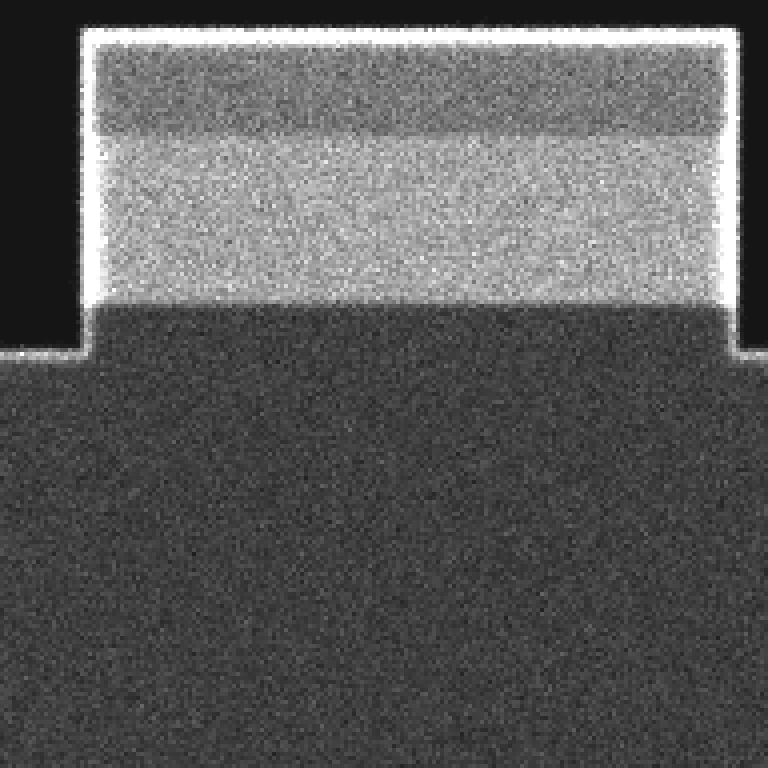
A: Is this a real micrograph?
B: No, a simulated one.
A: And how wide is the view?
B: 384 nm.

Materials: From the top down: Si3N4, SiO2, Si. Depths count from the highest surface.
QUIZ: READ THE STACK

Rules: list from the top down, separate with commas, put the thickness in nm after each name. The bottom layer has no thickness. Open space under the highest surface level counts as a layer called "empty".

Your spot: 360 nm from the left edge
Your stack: Si3N4 52, SiO2 84, Si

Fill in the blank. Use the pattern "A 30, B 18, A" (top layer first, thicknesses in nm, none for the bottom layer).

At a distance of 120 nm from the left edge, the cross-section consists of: Si3N4 52, SiO2 84, Si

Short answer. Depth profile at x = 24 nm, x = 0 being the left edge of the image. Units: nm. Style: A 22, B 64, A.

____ empty 160, Si